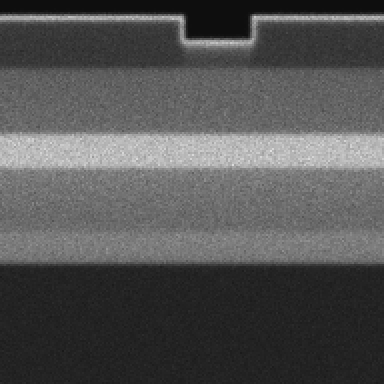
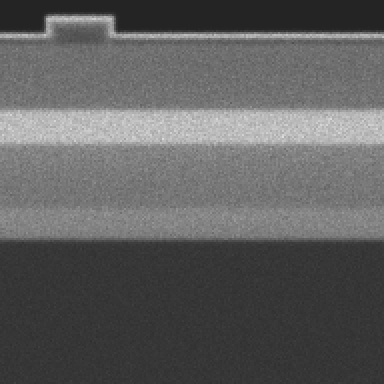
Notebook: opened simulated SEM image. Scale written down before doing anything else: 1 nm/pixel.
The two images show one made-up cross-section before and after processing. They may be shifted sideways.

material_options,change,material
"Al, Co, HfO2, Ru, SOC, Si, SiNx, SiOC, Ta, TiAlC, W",removed,SiNx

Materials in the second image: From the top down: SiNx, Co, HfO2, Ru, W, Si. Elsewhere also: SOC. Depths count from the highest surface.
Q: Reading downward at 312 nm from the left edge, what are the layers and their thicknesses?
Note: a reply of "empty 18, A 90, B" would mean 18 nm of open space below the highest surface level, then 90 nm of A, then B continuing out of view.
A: empty 18, SiNx 10, Co 66, HfO2 34, Ru 64, W 32, Si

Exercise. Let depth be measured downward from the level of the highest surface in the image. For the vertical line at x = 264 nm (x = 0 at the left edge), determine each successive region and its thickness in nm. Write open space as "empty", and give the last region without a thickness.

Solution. empty 18, SiNx 10, Co 66, HfO2 34, Ru 64, W 32, Si